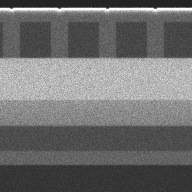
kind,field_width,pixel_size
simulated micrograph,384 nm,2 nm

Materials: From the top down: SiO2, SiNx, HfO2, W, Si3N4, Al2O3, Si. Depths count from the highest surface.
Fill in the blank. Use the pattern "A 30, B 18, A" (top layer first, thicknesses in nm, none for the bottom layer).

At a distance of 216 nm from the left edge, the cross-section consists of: empty 2, SiO2 98, HfO2 84, W 52, Si3N4 50, Al2O3 28, Si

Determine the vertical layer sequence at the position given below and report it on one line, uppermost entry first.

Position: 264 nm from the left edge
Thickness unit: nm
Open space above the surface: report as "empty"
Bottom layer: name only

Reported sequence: SiO2 28, SiNx 72, HfO2 84, W 52, Si3N4 50, Al2O3 28, Si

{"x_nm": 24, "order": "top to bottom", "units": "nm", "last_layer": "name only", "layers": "empty 2, SiO2 98, HfO2 84, W 52, Si3N4 50, Al2O3 28, Si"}